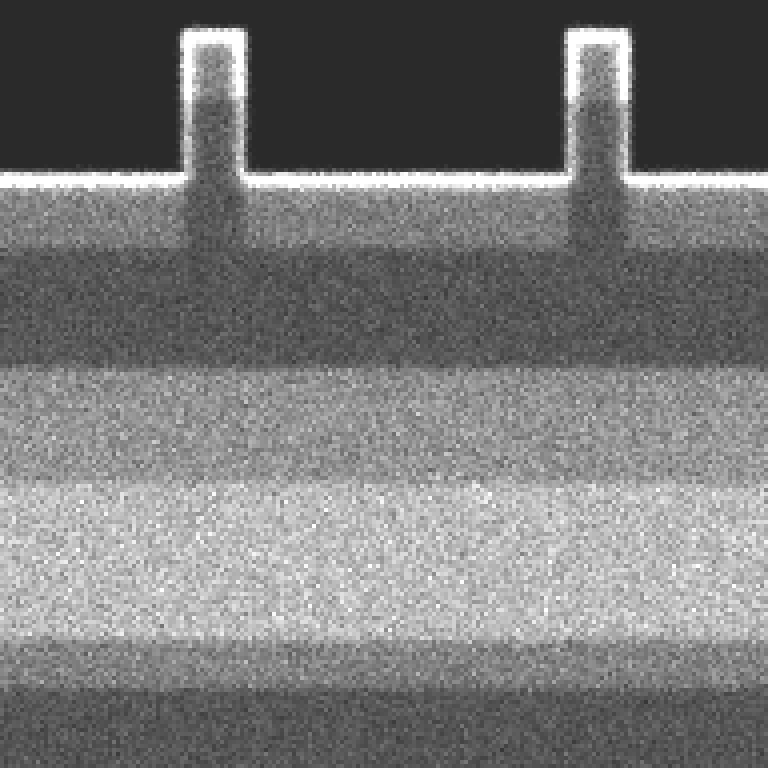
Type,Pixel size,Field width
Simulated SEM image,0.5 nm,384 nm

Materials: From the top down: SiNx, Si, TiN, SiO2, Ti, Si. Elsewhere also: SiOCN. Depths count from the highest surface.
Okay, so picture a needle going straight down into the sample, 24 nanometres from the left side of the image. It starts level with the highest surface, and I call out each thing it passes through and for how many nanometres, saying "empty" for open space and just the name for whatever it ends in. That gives empty 72, SiNx 36, Si 60, TiN 58, SiO2 78, Ti 24, Si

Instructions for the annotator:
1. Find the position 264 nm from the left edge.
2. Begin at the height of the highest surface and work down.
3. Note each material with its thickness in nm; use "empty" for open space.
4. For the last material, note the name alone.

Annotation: empty 72, SiNx 36, Si 60, TiN 58, SiO2 78, Ti 24, Si